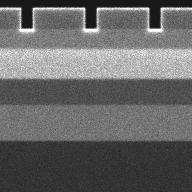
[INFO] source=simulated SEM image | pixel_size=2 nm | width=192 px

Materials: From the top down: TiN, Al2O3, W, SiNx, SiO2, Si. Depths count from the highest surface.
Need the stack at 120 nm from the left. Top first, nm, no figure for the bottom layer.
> TiN 42, Al2O3 40, W 60, SiNx 52, SiO2 72, Si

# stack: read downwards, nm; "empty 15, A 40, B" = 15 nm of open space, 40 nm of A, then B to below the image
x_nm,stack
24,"TiN 42, Al2O3 40, W 60, SiNx 52, SiO2 72, Si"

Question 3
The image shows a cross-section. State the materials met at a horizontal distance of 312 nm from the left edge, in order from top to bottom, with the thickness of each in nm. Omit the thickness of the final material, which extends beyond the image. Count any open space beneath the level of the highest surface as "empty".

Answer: empty 42, Al2O3 40, W 60, SiNx 52, SiO2 72, Si